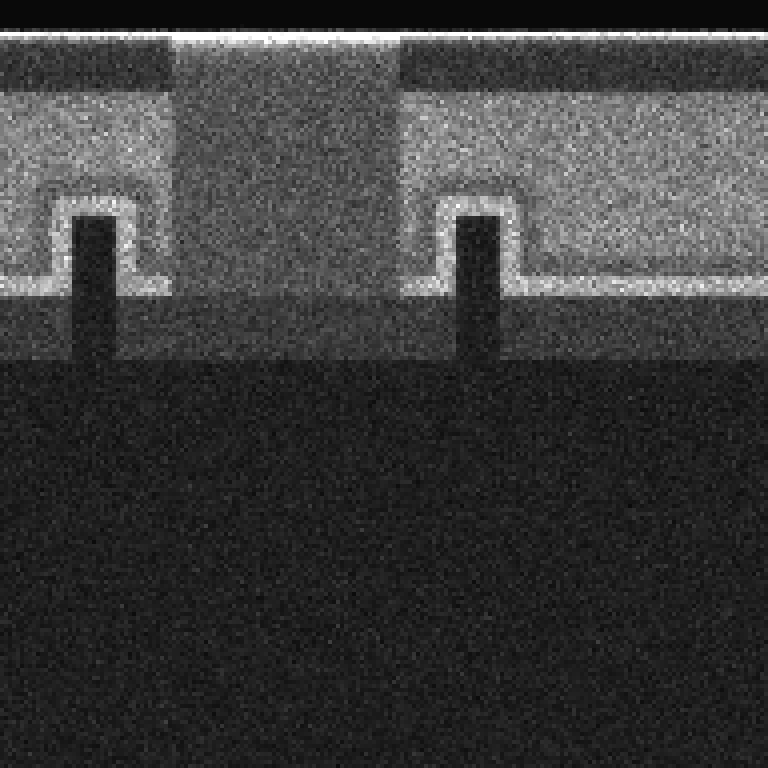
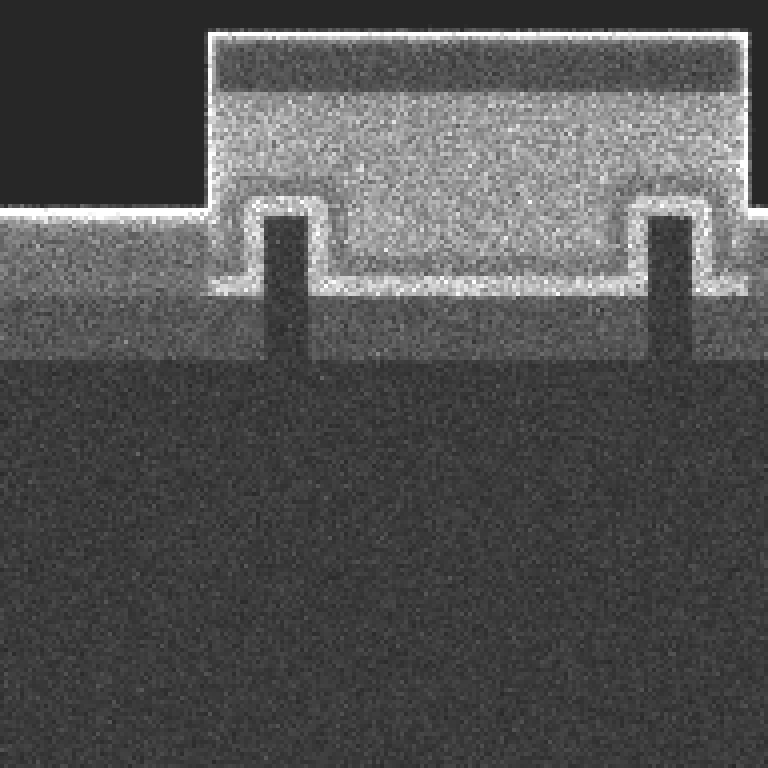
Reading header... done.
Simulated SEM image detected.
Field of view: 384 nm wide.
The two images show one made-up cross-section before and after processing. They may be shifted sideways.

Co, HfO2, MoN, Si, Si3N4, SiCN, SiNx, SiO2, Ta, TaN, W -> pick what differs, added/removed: SiO2 removed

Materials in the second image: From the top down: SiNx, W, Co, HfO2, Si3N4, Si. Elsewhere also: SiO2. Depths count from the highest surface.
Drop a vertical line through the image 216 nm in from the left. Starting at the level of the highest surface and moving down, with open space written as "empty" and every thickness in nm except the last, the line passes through SiNx 30, W 82, Co 10, HfO2 10, Si3N4 32, Si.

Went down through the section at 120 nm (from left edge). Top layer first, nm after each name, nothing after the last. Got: SiNx 30, W 42, Co 50, HfO2 10, Si3N4 32, Si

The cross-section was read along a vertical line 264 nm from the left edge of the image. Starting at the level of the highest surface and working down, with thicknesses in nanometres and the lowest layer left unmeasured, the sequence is SiNx 30, W 82, Co 10, HfO2 10, Si3N4 32, Si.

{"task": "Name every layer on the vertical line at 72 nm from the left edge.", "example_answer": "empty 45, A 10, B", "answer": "empty 88, SiO2 44, Si3N4 32, Si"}